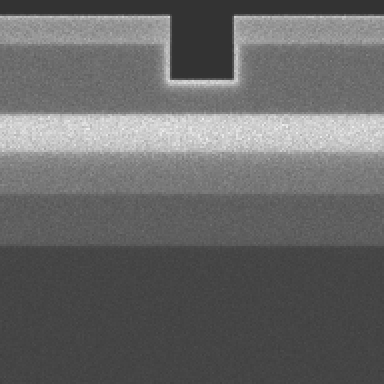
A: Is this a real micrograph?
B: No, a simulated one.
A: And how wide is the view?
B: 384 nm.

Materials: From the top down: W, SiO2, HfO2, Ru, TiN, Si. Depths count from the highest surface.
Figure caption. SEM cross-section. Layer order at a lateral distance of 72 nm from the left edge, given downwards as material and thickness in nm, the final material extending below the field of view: W 28, SiO2 70, HfO2 38, Ru 42, TiN 52, Si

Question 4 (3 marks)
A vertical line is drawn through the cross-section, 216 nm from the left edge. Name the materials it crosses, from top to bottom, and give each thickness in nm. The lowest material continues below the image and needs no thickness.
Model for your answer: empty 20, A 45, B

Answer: empty 64, SiO2 34, HfO2 38, Ru 42, TiN 52, Si